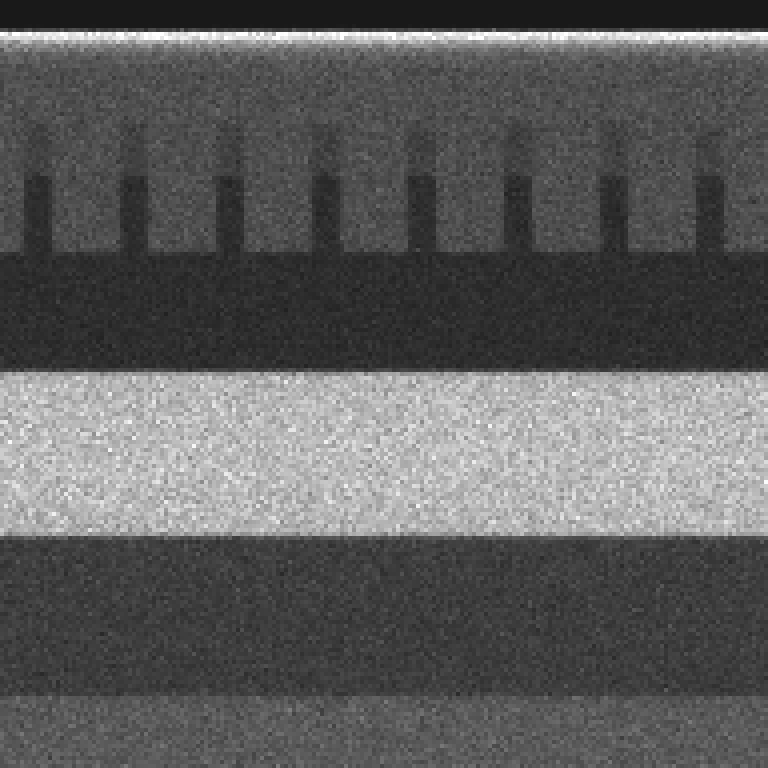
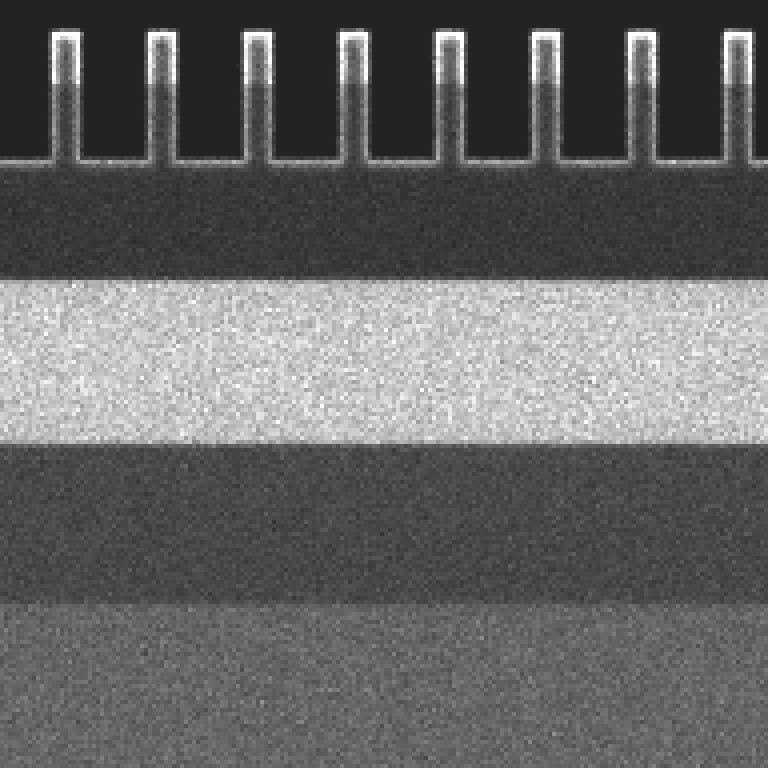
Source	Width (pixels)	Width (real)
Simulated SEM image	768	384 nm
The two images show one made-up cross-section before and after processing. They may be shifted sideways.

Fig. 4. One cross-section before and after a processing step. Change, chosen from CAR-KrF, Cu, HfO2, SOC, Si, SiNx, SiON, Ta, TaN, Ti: SOC removed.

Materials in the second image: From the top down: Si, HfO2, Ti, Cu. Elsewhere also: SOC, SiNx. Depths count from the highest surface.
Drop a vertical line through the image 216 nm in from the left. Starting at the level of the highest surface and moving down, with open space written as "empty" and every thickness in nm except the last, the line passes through empty 64, Si 60, HfO2 82, Ti 80, Cu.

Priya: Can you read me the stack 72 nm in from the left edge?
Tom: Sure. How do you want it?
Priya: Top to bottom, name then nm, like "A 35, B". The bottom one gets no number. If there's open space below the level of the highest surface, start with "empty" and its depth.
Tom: empty 64, Si 60, HfO2 82, Ti 80, Cu